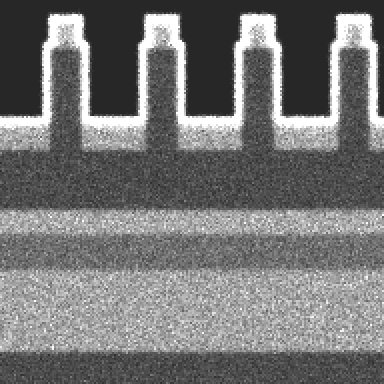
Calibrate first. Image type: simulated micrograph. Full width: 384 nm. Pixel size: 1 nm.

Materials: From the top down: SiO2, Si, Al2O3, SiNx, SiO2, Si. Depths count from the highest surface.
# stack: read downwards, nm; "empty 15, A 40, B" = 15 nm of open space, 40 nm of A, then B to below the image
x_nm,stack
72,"SiO2 32, Si 162, Al2O3 24, SiNx 36, SiO2 82, Si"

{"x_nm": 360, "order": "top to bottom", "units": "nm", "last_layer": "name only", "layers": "SiO2 32, Si 162, Al2O3 24, SiNx 36, SiO2 82, Si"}